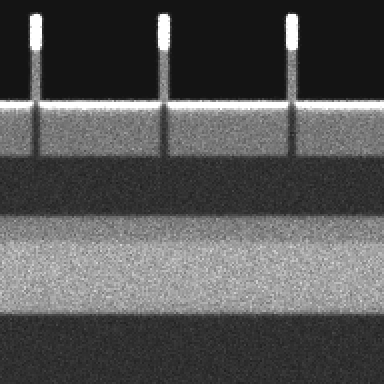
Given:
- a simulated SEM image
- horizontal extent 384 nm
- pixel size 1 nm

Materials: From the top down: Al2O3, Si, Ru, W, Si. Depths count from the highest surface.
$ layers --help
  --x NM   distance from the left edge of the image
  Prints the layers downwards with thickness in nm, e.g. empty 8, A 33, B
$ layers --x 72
empty 86, Al2O3 54, Si 60, Ru 26, W 72, Si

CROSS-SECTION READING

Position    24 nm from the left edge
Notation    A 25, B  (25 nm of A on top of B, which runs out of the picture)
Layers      empty 86, Al2O3 54, Si 60, Ru 26, W 72, Si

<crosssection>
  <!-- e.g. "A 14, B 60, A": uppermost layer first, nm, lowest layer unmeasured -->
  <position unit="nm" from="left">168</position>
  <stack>empty 86, Al2O3 54, Si 60, Ru 26, W 72, Si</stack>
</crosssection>